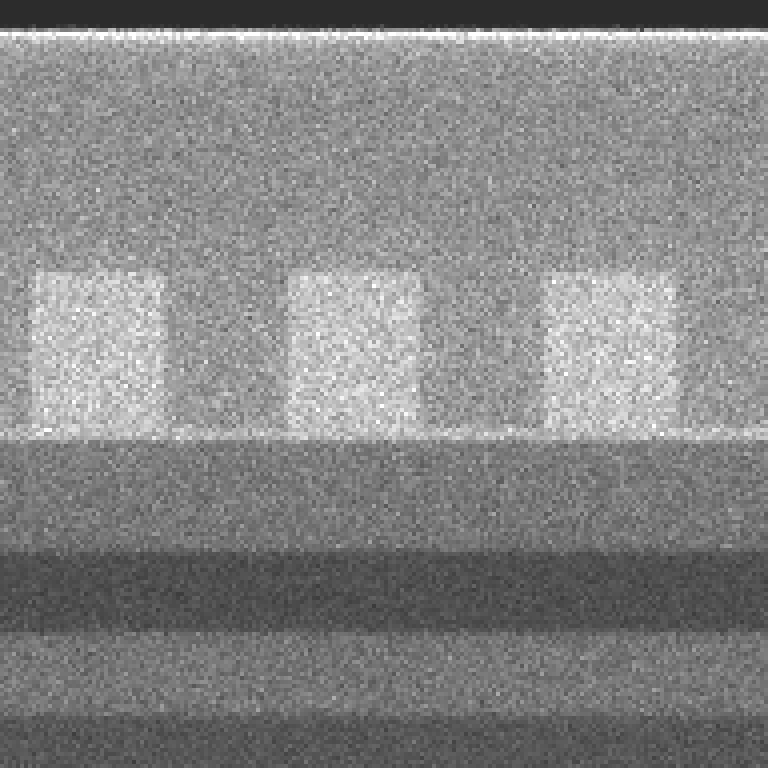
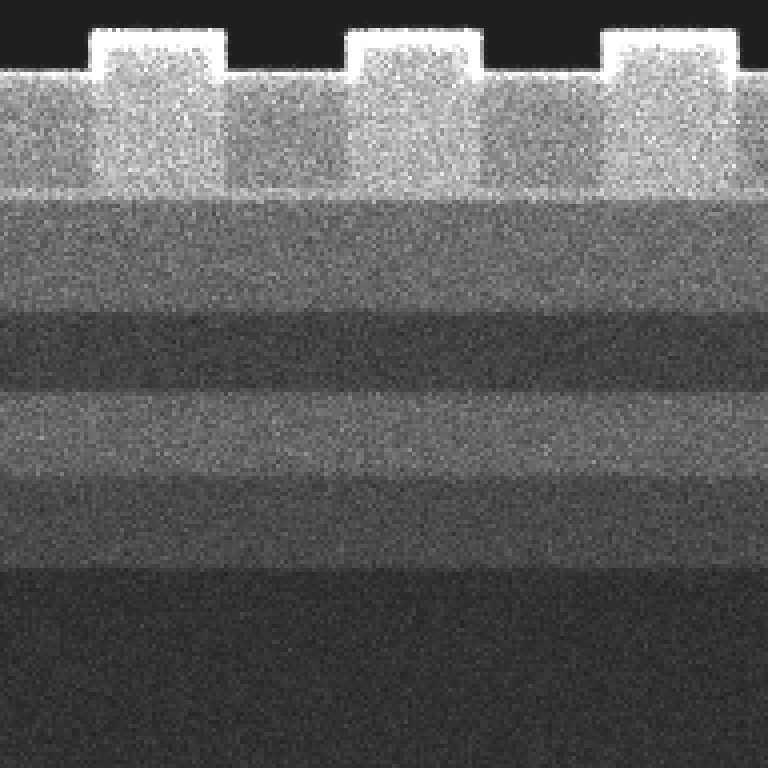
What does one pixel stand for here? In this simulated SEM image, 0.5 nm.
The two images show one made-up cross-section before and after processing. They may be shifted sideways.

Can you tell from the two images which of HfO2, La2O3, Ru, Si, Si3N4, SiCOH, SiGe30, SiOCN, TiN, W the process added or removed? Yes, it removed W.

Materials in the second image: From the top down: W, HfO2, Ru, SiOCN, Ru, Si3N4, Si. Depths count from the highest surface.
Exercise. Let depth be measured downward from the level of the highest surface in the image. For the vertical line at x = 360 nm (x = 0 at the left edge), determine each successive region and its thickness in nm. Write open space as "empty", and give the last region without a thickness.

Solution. HfO2 84, Ru 56, SiOCN 40, Ru 42, Si3N4 46, Si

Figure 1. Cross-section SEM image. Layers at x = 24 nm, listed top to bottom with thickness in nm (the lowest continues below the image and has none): empty 20, W 58, HfO2 6, Ru 56, SiOCN 40, Ru 42, Si3N4 46, Si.